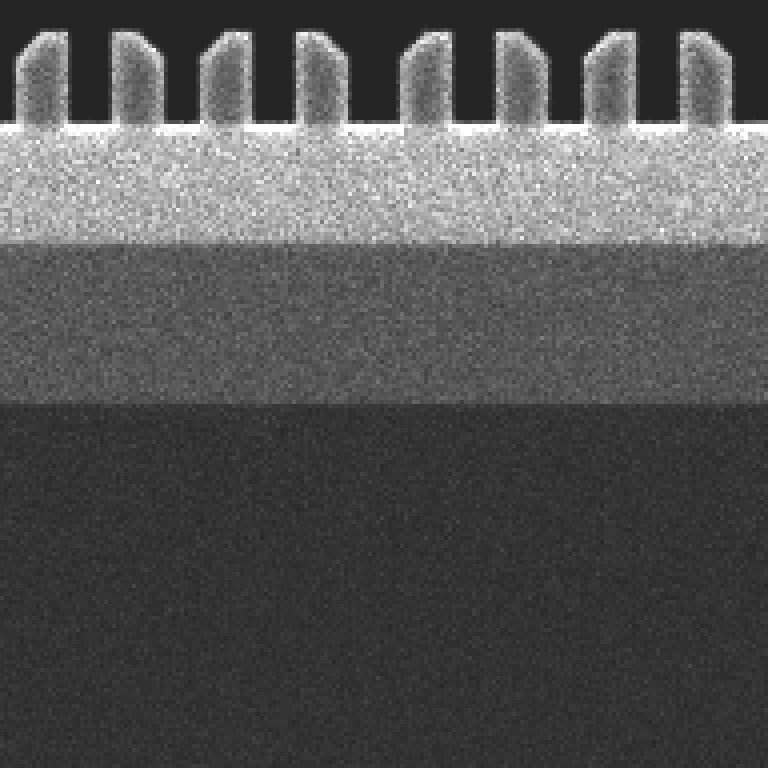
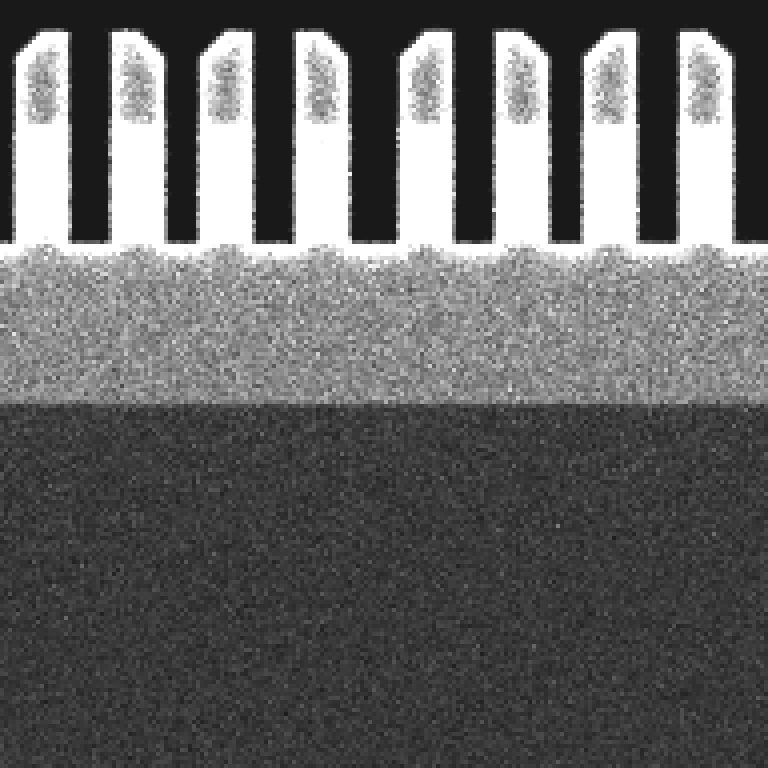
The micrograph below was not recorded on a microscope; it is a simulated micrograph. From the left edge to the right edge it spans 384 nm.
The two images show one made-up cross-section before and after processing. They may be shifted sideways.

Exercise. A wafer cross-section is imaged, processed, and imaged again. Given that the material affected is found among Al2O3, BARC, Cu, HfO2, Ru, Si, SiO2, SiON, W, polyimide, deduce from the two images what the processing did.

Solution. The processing removed HfO2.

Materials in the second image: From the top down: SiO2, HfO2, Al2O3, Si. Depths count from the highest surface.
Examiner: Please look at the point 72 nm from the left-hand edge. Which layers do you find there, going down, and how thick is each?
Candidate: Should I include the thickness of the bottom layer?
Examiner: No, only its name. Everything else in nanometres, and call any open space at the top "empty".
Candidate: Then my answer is empty 4, SiO2 42, HfO2 60, Al2O3 80, Si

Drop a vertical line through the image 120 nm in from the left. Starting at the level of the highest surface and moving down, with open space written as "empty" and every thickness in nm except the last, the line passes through SiO2 46, HfO2 60, Al2O3 80, Si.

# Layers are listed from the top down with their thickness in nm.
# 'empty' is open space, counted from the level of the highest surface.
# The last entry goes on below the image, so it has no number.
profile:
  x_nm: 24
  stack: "SiO2 46, HfO2 60, Al2O3 80, Si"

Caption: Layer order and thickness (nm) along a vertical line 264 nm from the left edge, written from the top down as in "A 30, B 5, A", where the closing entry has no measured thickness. empty 4, SiO2 42, HfO2 60, Al2O3 80, Si